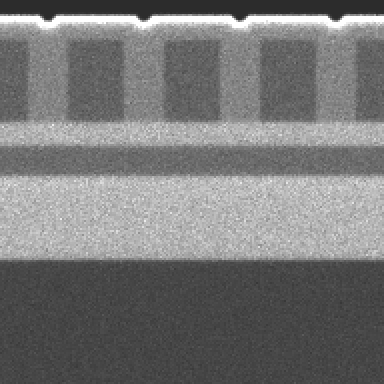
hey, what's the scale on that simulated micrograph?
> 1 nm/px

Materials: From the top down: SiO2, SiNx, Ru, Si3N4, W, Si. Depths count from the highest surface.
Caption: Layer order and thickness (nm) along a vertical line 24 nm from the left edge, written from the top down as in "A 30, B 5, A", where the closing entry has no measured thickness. SiO2 24, SiNx 82, Ru 24, Si3N4 30, W 84, Si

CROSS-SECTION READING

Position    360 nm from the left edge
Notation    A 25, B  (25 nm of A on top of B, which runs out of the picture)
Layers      SiO2 24, SiNx 82, Ru 24, Si3N4 30, W 84, Si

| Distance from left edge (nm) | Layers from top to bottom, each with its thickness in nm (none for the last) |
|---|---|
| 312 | SiO2 24, SiNx 82, Ru 24, Si3N4 30, W 84, Si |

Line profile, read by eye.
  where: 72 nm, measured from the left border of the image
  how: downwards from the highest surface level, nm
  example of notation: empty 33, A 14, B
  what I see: SiO2 24, SiNx 82, Ru 24, Si3N4 30, W 84, Si